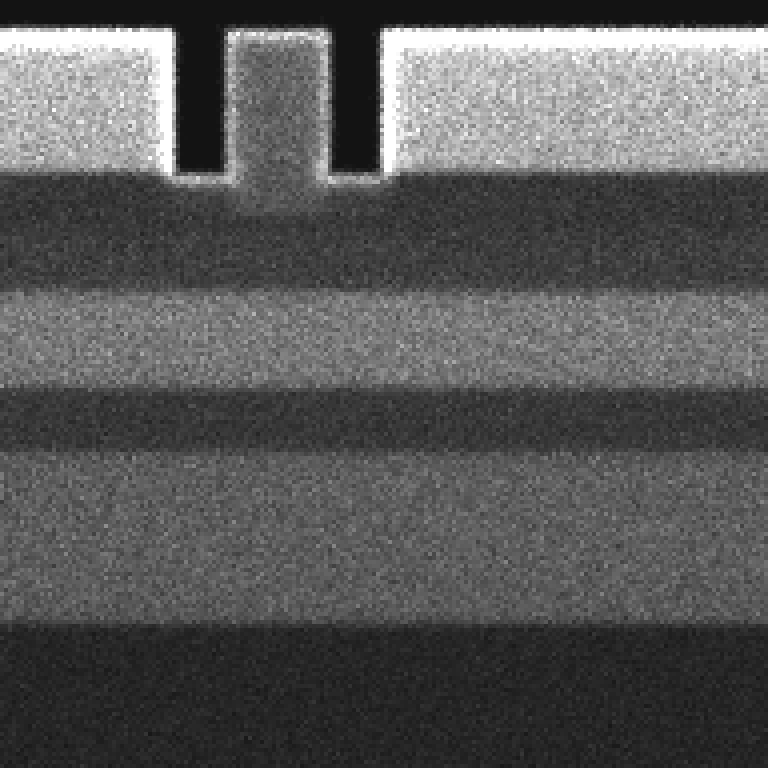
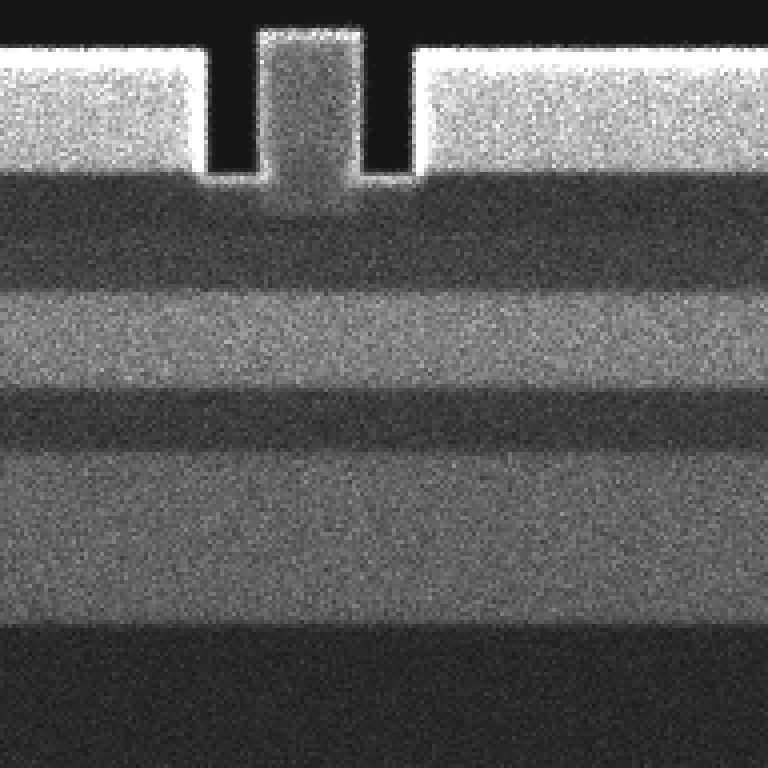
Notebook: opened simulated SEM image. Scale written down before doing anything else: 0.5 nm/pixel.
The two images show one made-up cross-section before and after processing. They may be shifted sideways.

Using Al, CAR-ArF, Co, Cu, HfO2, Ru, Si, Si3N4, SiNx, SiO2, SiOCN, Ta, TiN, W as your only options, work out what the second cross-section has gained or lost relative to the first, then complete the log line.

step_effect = removed HfO2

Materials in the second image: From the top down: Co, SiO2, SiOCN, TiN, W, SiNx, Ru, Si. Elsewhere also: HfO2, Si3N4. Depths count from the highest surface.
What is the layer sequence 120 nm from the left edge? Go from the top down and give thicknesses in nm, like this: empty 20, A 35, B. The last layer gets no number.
empty 72, Si3N4 20, SiOCN 8, TiN 30, W 48, SiNx 32, Ru 86, Si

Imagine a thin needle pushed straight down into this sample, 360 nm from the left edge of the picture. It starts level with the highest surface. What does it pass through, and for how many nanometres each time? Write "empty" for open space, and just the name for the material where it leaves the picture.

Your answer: empty 10, HfO2 60, SiOCN 30, TiN 30, W 48, SiNx 32, Ru 86, Si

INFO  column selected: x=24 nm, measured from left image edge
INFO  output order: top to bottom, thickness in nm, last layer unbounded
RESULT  empty 10, HfO2 60, SiOCN 30, TiN 30, W 48, SiNx 32, Ru 86, Si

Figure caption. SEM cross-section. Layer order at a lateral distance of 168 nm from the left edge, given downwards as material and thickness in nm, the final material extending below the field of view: Co 64, SiO2 28, SiOCN 8, TiN 30, W 48, SiNx 32, Ru 86, Si